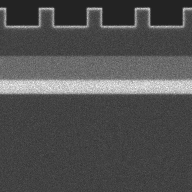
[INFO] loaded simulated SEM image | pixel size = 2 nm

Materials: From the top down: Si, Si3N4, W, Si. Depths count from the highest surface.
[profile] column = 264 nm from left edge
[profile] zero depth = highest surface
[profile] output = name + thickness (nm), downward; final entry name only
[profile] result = empty 36, Si 60, Si3N4 48, W 28, Si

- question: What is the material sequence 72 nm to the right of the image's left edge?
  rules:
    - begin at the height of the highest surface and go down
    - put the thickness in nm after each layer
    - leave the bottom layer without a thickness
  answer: empty 36, Si 60, Si3N4 48, W 28, Si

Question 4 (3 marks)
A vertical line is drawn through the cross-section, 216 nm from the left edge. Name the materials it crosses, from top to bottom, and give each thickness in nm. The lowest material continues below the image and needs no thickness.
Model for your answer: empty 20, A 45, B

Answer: empty 36, Si 60, Si3N4 48, W 28, Si